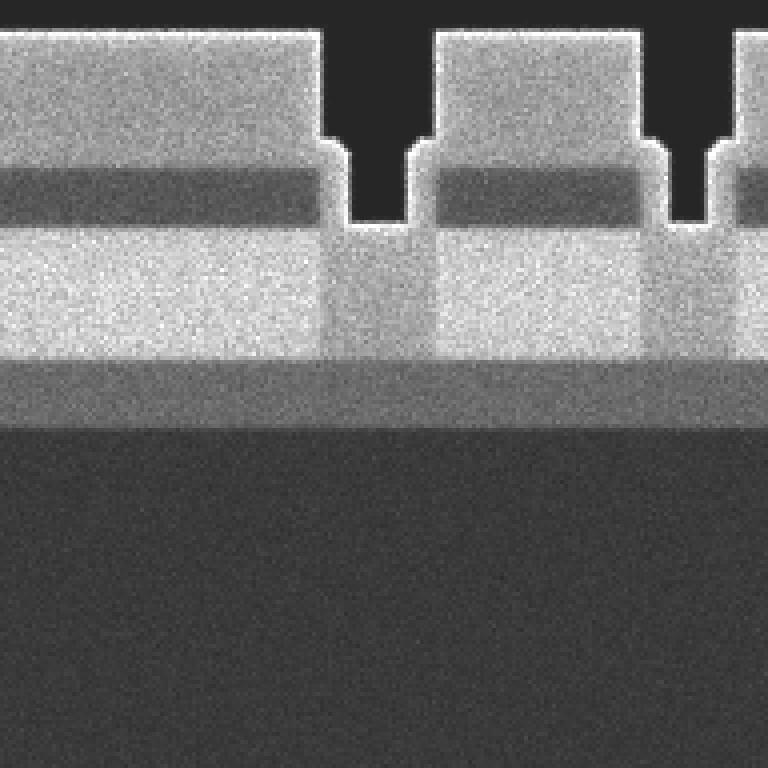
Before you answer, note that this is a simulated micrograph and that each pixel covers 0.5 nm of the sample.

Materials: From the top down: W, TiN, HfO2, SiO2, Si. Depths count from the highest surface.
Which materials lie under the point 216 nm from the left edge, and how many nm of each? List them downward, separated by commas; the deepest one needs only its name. empty 54, W 110, SiO2 34, Si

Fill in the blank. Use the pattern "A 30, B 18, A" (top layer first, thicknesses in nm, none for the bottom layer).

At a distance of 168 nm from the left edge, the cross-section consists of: empty 56, W 108, SiO2 34, Si